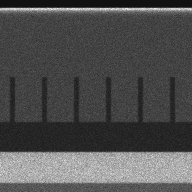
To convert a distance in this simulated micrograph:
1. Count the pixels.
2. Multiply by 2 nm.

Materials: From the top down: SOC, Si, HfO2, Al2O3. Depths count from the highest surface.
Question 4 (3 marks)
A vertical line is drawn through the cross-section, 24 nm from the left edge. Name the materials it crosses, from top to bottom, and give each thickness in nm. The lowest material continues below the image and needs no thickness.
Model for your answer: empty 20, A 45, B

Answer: SOC 138, Si 150, HfO2 62, Al2O3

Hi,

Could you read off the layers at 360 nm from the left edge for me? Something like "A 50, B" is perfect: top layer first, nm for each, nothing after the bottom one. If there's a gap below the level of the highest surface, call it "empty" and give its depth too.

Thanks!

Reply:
SOC 228, Si 60, HfO2 62, Al2O3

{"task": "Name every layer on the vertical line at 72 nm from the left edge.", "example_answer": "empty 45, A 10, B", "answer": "SOC 228, Si 60, HfO2 62, Al2O3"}